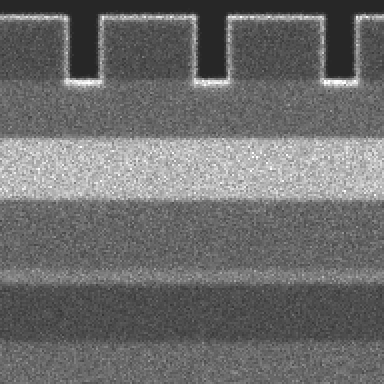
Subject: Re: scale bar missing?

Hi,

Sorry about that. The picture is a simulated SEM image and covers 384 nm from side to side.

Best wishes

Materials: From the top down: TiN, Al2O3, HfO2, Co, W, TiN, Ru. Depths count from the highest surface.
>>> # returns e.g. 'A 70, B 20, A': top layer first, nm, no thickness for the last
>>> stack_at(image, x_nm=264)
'TiN 64, Al2O3 58, HfO2 62, Co 70, W 14, TiN 58, Ru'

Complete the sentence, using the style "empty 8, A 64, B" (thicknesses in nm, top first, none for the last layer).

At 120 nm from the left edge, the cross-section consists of TiN 64, Al2O3 58, HfO2 62, Co 70, W 14, TiN 58, Ru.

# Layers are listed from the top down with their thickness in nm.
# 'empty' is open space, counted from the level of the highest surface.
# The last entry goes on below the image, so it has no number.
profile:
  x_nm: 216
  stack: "empty 64, Al2O3 58, HfO2 62, Co 70, W 14, TiN 58, Ru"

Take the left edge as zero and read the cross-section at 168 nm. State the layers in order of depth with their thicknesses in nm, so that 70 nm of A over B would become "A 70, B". TiN 64, Al2O3 58, HfO2 62, Co 70, W 14, TiN 58, Ru